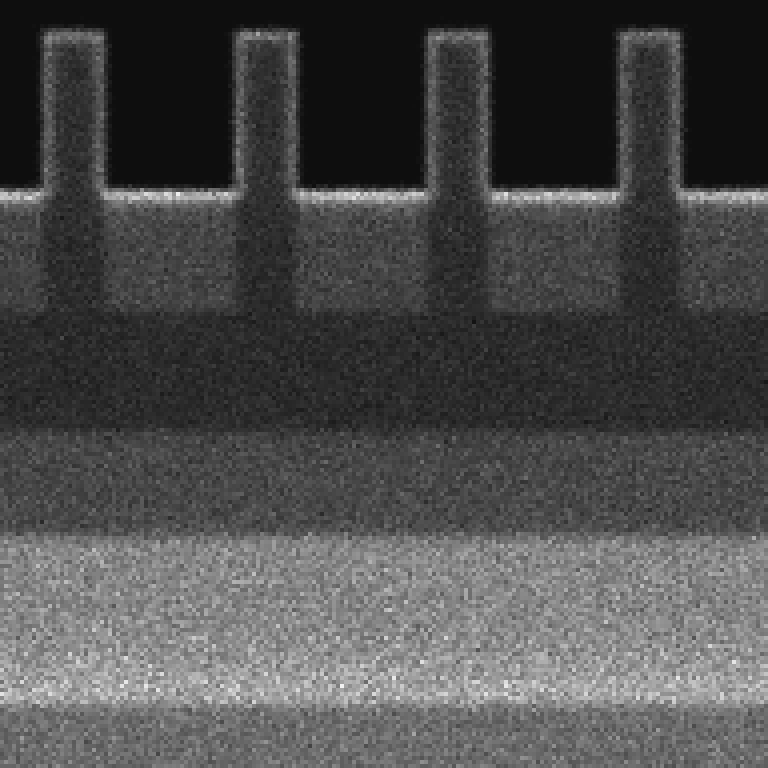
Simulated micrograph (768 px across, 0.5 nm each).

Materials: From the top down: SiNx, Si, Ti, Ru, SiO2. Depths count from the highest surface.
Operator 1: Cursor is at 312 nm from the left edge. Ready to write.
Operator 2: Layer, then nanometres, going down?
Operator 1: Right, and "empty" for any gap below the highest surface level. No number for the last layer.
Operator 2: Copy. Si 200, Ti 52, Ru 84, SiO2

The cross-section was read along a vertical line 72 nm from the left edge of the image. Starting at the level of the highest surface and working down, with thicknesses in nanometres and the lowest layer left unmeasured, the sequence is empty 80, SiNx 60, Si 60, Ti 52, Ru 84, SiO2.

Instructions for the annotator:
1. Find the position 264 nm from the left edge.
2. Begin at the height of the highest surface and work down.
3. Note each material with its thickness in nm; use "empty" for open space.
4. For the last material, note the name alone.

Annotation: empty 80, SiNx 60, Si 60, Ti 52, Ru 84, SiO2